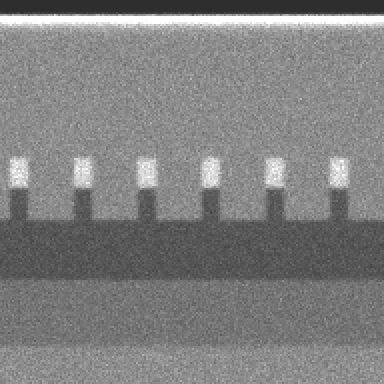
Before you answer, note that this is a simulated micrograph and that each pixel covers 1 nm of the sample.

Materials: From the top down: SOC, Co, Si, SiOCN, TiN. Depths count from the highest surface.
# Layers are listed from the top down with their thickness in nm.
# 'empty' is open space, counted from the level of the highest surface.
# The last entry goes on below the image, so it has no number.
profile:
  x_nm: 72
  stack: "SOC 204, Si 60, SiOCN 66, TiN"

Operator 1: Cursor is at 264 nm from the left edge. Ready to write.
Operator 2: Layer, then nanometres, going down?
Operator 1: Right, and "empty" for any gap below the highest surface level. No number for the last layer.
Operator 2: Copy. SOC 204, Si 60, SiOCN 66, TiN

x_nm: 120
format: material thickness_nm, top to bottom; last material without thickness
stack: SOC 204, Si 60, SiOCN 66, TiN